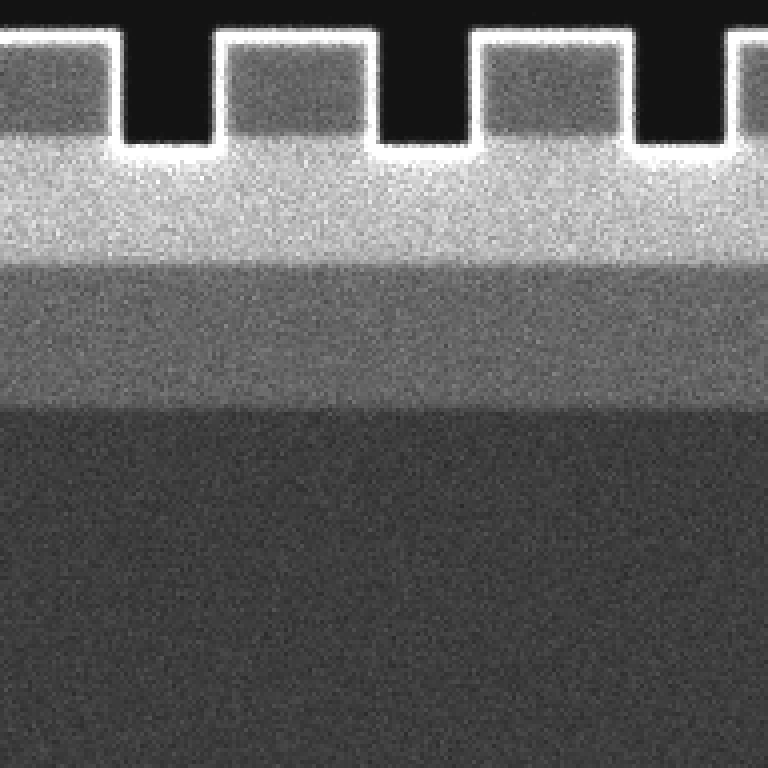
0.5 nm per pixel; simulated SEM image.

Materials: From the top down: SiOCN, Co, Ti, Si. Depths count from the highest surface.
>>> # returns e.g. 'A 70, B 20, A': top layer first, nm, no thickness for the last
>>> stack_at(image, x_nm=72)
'empty 58, Co 58, Ti 72, Si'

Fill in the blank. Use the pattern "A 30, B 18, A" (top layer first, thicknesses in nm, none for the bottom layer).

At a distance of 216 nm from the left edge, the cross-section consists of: empty 58, Co 58, Ti 72, Si